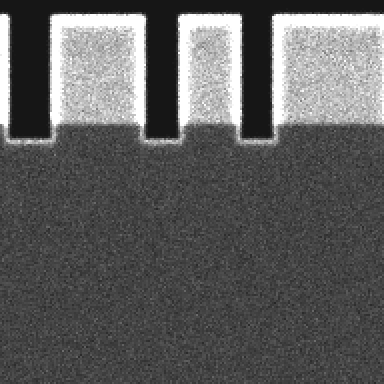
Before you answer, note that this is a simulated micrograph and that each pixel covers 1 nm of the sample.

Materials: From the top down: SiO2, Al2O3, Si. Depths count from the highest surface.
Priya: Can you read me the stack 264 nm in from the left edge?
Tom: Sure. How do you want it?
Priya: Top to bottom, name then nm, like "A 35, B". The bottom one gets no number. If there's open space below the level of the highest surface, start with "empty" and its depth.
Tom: empty 124, Si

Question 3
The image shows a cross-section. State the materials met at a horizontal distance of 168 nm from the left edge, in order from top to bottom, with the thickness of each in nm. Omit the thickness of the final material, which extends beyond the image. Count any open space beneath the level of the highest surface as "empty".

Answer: empty 124, Si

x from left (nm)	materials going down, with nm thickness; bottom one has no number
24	empty 124, Si